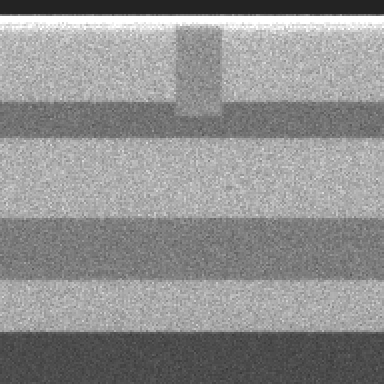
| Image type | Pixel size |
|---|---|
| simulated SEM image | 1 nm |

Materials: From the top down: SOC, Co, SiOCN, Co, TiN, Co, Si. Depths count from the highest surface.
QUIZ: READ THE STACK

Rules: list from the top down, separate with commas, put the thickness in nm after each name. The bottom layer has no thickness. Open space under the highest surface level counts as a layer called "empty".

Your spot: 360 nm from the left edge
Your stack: SOC 10, Co 76, SiOCN 36, Co 80, TiN 62, Co 52, Si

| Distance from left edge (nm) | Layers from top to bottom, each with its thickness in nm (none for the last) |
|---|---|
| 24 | SOC 10, Co 76, SiOCN 36, Co 80, TiN 62, Co 52, Si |